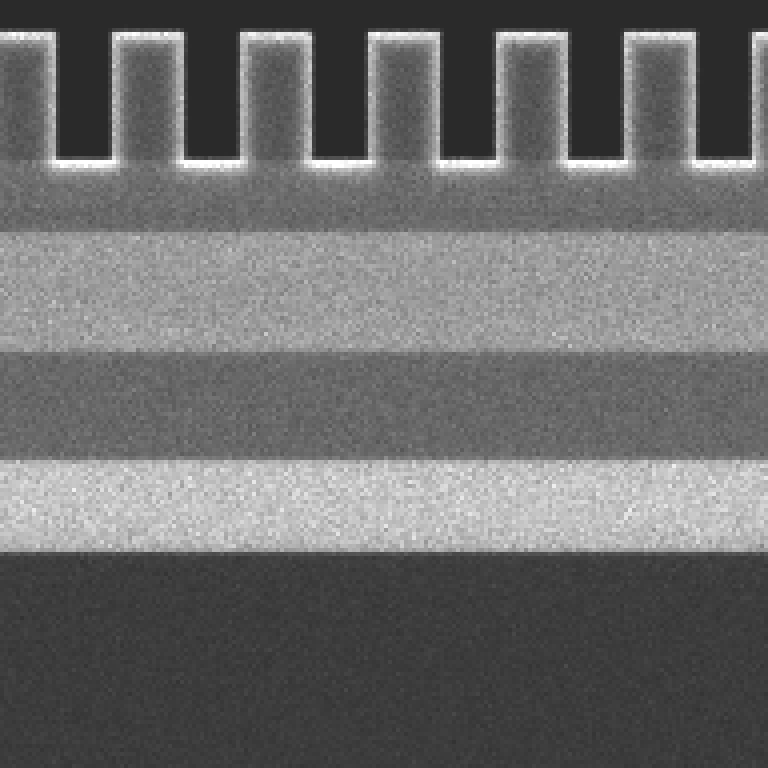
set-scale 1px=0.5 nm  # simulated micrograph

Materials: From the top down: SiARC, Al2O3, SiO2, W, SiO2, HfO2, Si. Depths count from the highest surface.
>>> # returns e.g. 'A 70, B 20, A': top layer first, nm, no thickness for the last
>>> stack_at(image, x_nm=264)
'SiARC 64, Al2O3 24, SiO2 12, W 60, SiO2 54, HfO2 46, Si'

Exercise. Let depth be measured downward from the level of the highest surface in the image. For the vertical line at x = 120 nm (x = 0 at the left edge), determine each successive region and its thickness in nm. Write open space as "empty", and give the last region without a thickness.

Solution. SiARC 64, Al2O3 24, SiO2 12, W 60, SiO2 54, HfO2 46, Si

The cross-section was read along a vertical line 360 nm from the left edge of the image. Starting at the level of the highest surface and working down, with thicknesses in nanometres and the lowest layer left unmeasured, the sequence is empty 64, Al2O3 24, SiO2 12, W 60, SiO2 54, HfO2 46, Si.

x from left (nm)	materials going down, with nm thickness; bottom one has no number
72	SiARC 64, Al2O3 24, SiO2 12, W 60, SiO2 54, HfO2 46, Si